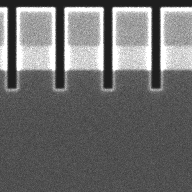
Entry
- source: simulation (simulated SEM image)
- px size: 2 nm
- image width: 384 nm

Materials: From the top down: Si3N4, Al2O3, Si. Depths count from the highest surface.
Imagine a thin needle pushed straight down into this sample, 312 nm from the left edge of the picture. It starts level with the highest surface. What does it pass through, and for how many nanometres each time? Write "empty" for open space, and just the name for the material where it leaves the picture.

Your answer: empty 162, Si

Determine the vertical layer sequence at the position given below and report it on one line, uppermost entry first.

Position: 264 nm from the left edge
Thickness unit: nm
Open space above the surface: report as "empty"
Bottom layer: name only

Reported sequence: Si3N4 76, Al2O3 48, Si